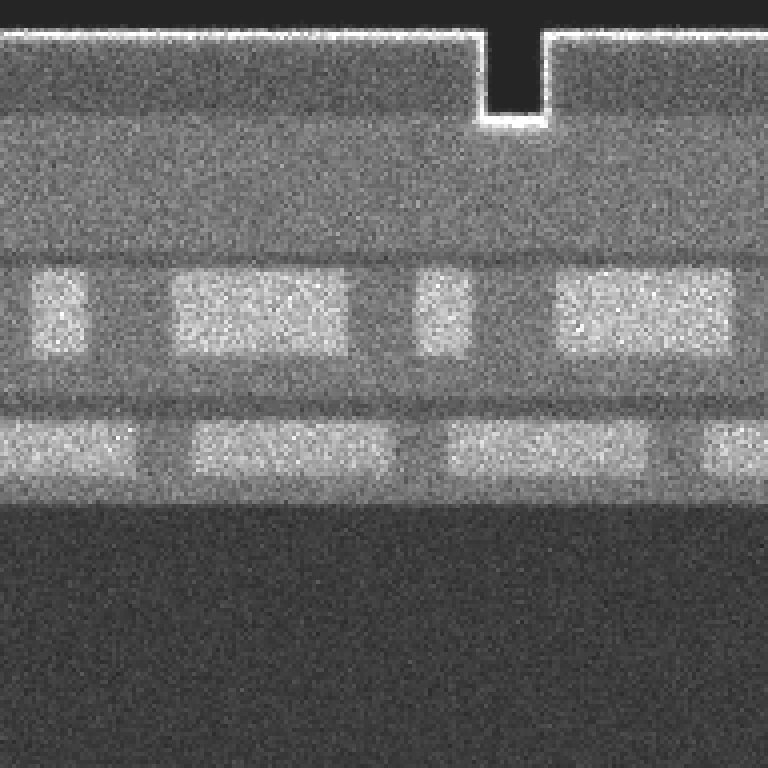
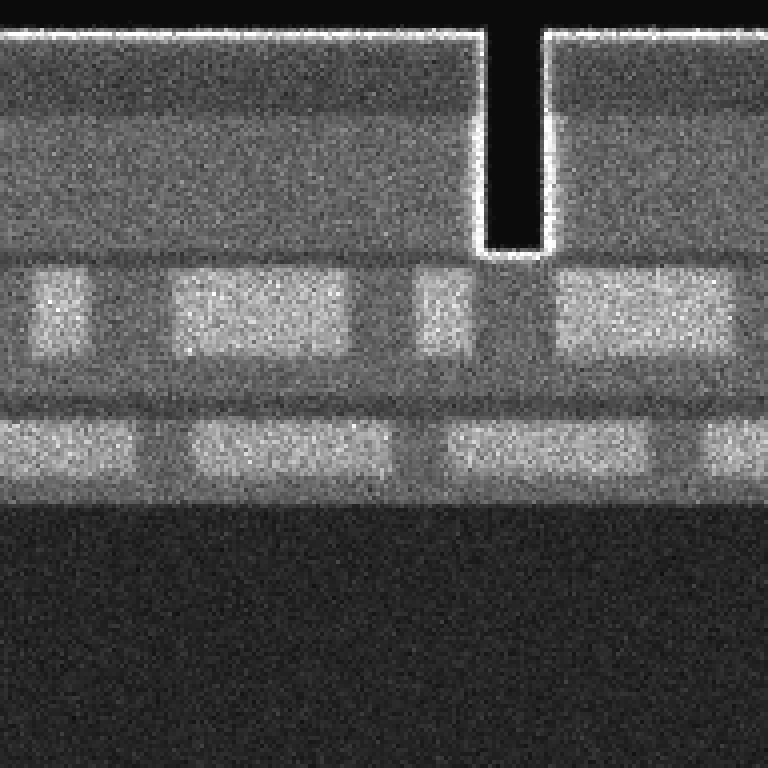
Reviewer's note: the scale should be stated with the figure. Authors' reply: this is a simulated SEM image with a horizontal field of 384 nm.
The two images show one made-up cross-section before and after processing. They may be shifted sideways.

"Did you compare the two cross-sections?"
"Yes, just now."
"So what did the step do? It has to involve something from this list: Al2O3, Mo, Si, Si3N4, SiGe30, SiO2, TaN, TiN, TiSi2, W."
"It removed SiO2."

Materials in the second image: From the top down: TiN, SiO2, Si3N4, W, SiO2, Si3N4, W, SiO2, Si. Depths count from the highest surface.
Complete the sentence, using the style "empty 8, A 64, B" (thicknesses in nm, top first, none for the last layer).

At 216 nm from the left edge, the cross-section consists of TiN 42, SiO2 68, Si3N4 8, W 44, SiO2 20, Si3N4 12, SiO2 42, Si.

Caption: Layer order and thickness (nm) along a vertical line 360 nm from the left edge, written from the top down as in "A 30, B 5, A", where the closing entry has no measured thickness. TiN 42, SiO2 68, Si3N4 8, W 44, SiO2 20, Si3N4 12, W 28, SiO2 14, Si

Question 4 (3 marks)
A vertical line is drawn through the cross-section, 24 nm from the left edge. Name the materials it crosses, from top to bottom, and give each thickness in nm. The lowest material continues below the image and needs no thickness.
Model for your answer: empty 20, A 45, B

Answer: TiN 42, SiO2 68, Si3N4 8, W 44, SiO2 20, Si3N4 12, W 28, SiO2 14, Si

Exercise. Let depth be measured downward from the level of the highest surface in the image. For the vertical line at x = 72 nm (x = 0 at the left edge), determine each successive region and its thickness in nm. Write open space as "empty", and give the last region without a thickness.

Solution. TiN 42, SiO2 68, Si3N4 8, SiO2 64, Si3N4 12, SiO2 42, Si